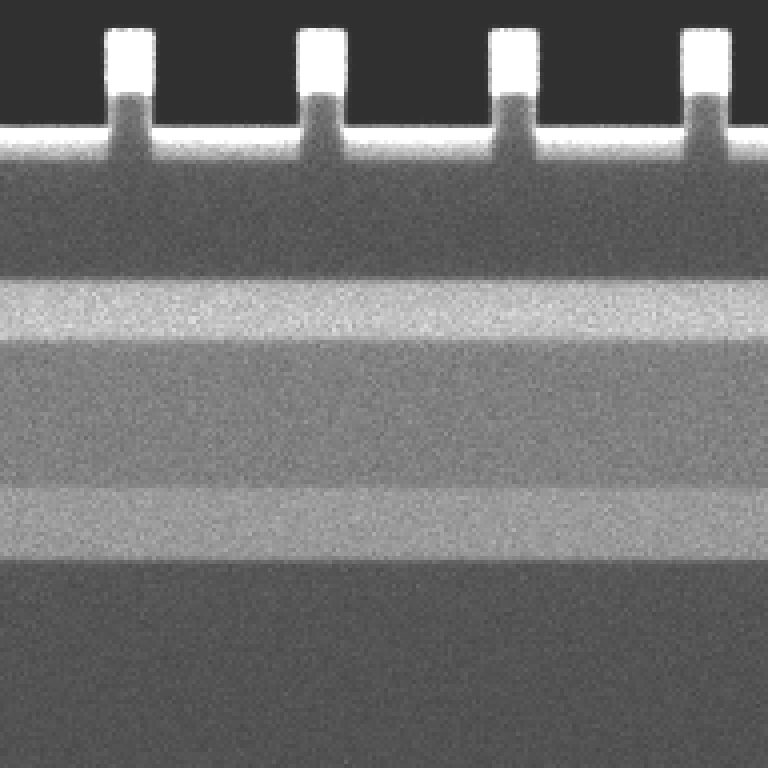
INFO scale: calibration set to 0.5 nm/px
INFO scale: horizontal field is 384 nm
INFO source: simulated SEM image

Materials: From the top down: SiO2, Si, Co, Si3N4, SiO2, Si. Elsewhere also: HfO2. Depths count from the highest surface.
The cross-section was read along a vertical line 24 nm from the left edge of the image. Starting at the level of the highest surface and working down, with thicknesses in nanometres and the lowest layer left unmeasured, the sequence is empty 48, SiO2 16, Si 60, Co 30, Si3N4 74, SiO2 36, Si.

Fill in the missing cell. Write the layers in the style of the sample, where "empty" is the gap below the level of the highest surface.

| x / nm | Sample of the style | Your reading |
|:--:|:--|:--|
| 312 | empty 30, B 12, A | empty 48, SiO2 16, Si 60, Co 30, Si3N4 74, SiO2 36, Si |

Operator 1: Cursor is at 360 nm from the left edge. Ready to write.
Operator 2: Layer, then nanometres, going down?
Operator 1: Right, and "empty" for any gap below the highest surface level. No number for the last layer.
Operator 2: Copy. HfO2 30, Si 94, Co 30, Si3N4 74, SiO2 36, Si